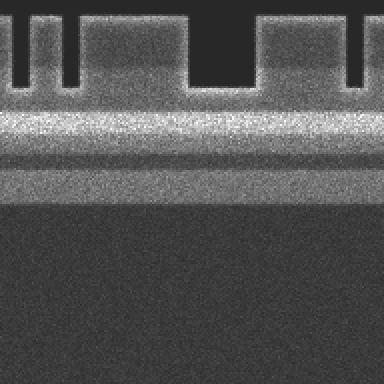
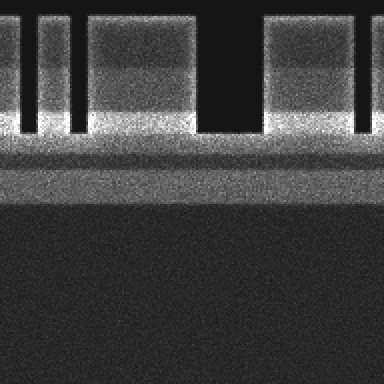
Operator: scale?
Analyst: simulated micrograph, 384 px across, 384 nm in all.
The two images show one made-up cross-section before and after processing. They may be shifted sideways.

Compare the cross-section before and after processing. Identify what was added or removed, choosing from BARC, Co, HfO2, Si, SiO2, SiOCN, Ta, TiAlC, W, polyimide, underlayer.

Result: HfO2 and SiO2 removed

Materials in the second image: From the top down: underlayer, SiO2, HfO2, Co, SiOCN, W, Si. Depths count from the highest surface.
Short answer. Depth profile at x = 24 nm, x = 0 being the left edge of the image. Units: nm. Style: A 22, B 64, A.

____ empty 118, Co 20, SiOCN 16, W 34, Si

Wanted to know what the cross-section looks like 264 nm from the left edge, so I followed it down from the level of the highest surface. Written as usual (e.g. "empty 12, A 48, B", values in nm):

underlayer 52, SiO2 44, HfO2 22, Co 20, SiOCN 16, W 34, Si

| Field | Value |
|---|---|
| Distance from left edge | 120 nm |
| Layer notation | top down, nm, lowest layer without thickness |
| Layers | underlayer 52, SiO2 44, HfO2 22, Co 20, SiOCN 16, W 34, Si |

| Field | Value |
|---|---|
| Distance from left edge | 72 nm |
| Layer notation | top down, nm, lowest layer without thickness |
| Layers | empty 118, Co 20, SiOCN 16, W 34, Si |